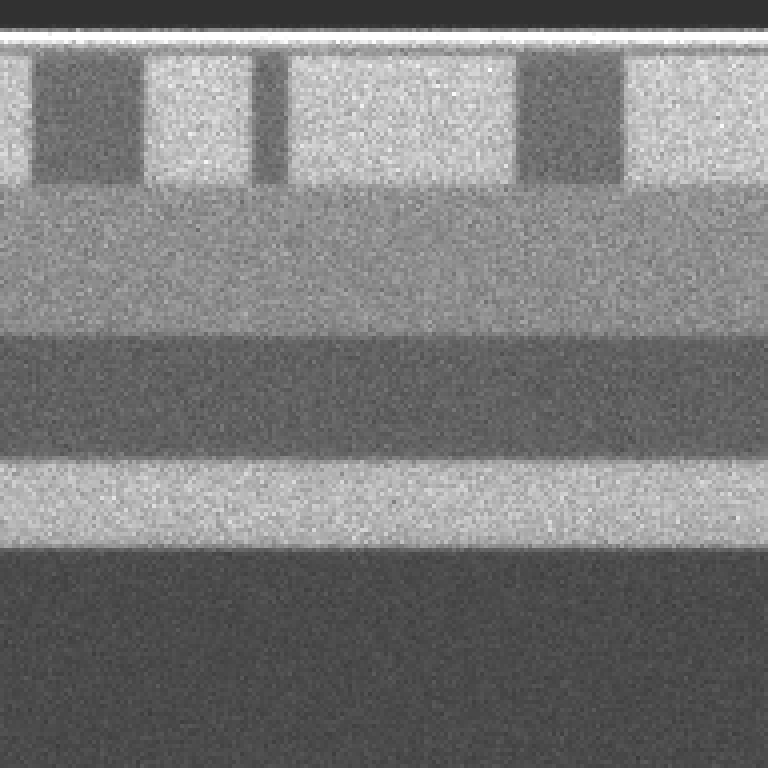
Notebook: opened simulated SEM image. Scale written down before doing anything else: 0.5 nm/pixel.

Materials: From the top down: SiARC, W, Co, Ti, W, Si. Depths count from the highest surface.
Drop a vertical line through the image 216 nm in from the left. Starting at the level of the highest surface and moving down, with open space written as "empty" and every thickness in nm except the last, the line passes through SiARC 12, W 64, Co 76, Ti 62, W 44, Si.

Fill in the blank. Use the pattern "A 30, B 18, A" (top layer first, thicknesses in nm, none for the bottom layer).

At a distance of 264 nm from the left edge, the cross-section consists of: SiARC 76, Co 76, Ti 62, W 44, Si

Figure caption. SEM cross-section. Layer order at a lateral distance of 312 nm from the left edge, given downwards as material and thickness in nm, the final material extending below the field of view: SiARC 12, W 64, Co 76, Ti 62, W 44, Si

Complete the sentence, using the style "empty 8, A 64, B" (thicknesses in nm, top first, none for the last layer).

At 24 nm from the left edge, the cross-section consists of SiARC 76, Co 76, Ti 62, W 44, Si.